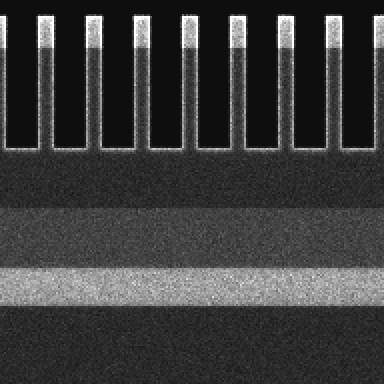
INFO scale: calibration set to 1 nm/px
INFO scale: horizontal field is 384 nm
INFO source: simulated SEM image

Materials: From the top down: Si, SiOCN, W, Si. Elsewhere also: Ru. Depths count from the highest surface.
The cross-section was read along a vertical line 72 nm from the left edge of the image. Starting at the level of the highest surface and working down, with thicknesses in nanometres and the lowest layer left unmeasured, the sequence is empty 132, Si 60, SiOCN 60, W 38, Si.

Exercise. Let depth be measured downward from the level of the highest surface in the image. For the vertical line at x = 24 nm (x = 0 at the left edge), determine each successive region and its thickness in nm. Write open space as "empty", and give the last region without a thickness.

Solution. empty 132, Si 60, SiOCN 60, W 38, Si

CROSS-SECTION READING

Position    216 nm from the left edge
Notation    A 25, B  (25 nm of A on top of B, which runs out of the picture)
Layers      empty 132, Si 60, SiOCN 60, W 38, Si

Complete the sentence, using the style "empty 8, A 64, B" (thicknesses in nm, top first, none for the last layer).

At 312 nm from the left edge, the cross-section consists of empty 132, Si 60, SiOCN 60, W 38, Si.